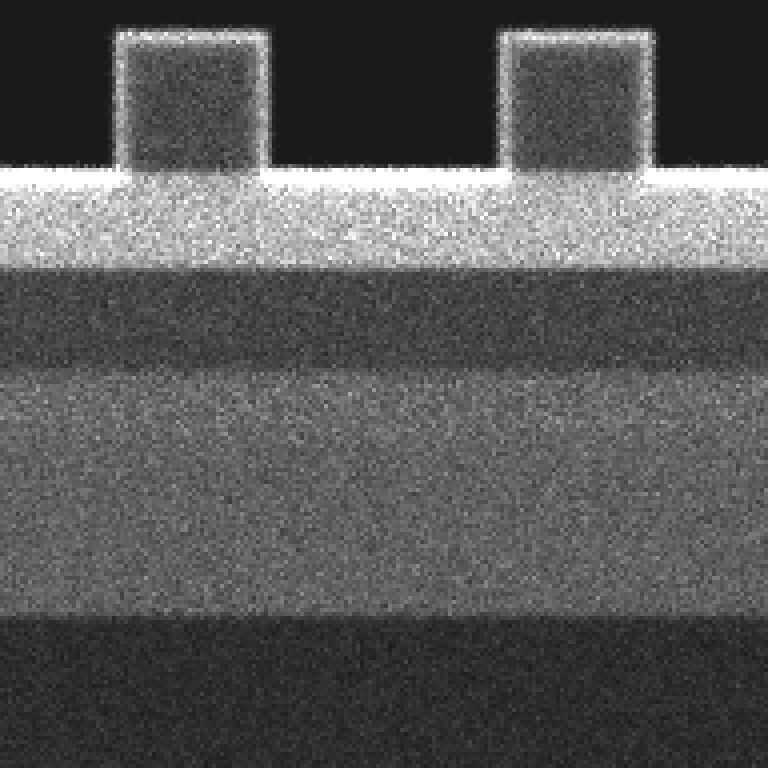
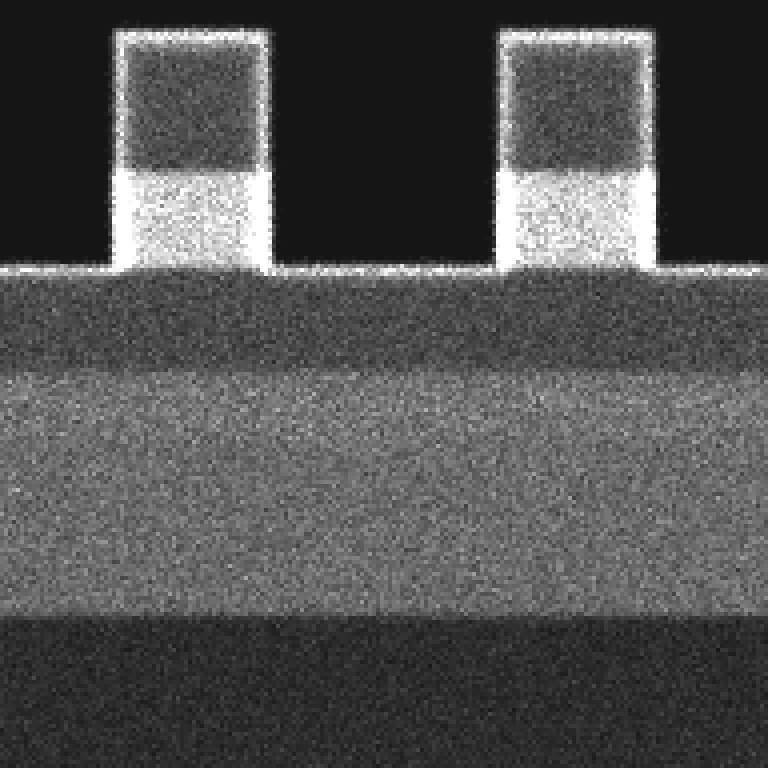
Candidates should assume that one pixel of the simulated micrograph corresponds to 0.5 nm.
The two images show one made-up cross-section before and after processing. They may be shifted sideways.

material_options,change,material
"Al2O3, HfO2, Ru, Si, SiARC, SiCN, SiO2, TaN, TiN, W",removed,HfO2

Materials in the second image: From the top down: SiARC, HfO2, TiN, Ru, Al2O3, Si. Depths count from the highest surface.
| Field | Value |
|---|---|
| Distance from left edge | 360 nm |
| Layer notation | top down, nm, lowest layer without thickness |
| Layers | empty 118, TiN 52, Ru 34, Al2O3 88, Si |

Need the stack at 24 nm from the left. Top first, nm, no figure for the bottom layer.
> empty 118, TiN 52, Ru 34, Al2O3 88, Si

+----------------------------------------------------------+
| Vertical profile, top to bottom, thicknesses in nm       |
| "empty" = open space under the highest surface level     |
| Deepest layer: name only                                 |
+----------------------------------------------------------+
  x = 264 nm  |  SiARC 70, HfO2 48, TiN 52, Ru 34, Al2O3 88, Si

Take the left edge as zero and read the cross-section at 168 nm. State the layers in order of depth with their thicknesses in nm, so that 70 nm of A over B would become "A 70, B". empty 118, TiN 52, Ru 34, Al2O3 88, Si